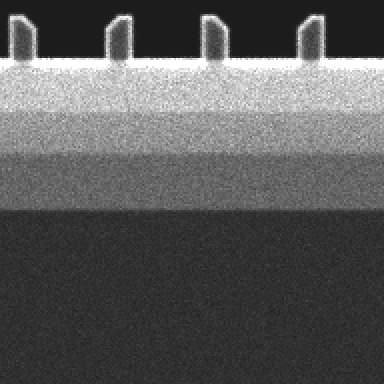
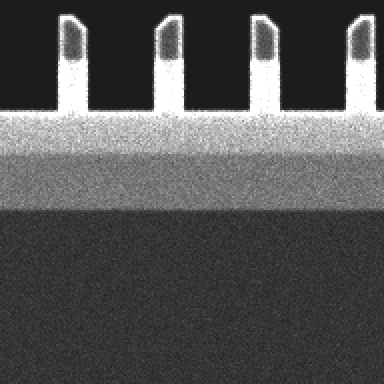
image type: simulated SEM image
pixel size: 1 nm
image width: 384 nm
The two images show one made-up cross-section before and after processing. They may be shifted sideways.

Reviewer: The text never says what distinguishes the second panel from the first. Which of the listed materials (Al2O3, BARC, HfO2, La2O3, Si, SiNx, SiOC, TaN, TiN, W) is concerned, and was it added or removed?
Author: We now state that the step removed HfO2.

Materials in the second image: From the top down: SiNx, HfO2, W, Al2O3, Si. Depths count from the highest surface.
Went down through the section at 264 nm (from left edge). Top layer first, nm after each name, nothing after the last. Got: SiNx 44, HfO2 52, W 42, Al2O3 56, Si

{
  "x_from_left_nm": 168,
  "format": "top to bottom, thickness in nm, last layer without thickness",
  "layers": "SiNx 44, HfO2 52, W 42, Al2O3 56, Si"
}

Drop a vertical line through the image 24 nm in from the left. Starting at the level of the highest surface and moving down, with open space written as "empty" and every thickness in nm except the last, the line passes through empty 96, W 42, Al2O3 56, Si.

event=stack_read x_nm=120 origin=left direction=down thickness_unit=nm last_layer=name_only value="empty 96, W 42, Al2O3 56, Si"